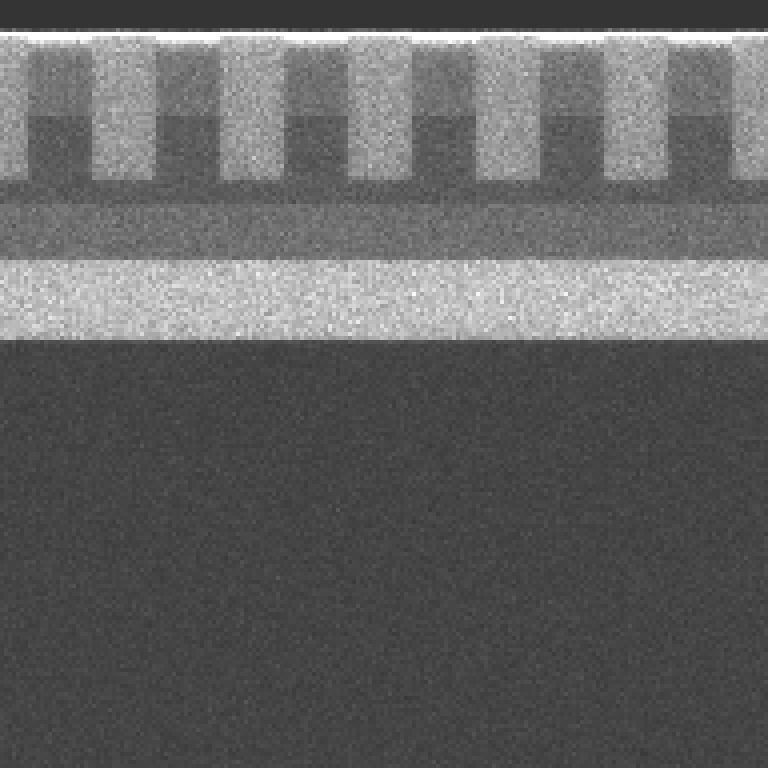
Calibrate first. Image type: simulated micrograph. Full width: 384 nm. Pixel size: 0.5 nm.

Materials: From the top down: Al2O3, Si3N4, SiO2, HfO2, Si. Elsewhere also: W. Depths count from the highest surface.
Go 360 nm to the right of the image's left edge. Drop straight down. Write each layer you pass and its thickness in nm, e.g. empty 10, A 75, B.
Al2O3 42, Si3N4 44, SiO2 28, HfO2 40, Si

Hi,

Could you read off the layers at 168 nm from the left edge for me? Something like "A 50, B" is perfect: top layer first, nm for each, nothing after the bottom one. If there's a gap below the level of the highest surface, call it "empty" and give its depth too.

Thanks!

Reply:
Al2O3 42, Si3N4 44, SiO2 28, HfO2 40, Si